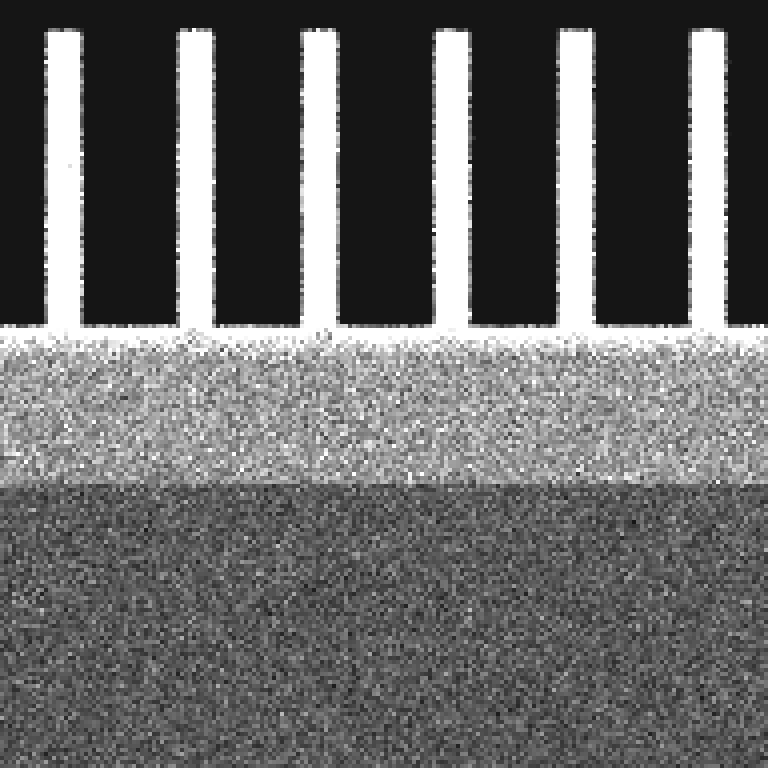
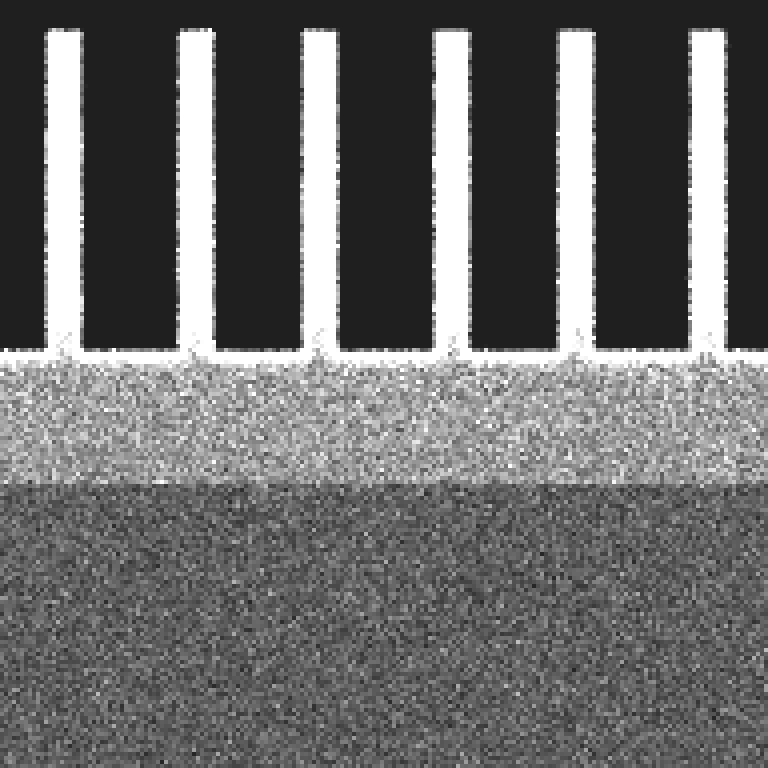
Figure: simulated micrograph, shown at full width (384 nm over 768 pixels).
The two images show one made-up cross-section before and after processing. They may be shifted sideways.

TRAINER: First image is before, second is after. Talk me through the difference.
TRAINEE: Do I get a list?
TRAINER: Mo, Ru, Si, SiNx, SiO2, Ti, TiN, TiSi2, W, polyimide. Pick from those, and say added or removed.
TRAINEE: removed: TiN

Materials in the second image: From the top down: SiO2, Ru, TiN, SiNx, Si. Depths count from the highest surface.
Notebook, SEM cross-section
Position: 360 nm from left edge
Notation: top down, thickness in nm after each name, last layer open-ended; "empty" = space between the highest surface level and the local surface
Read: SiO2 50, Ru 98, TiN 12, SiNx 66, Si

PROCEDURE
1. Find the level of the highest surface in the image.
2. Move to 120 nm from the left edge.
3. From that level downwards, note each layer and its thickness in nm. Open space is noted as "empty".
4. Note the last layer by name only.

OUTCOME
empty 160, SiNx 66, Si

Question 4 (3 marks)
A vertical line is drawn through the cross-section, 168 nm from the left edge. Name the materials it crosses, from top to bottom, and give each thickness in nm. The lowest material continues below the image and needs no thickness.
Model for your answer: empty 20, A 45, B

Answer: empty 160, SiNx 66, Si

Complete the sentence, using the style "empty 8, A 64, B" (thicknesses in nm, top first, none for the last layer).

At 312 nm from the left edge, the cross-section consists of empty 160, SiNx 66, Si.